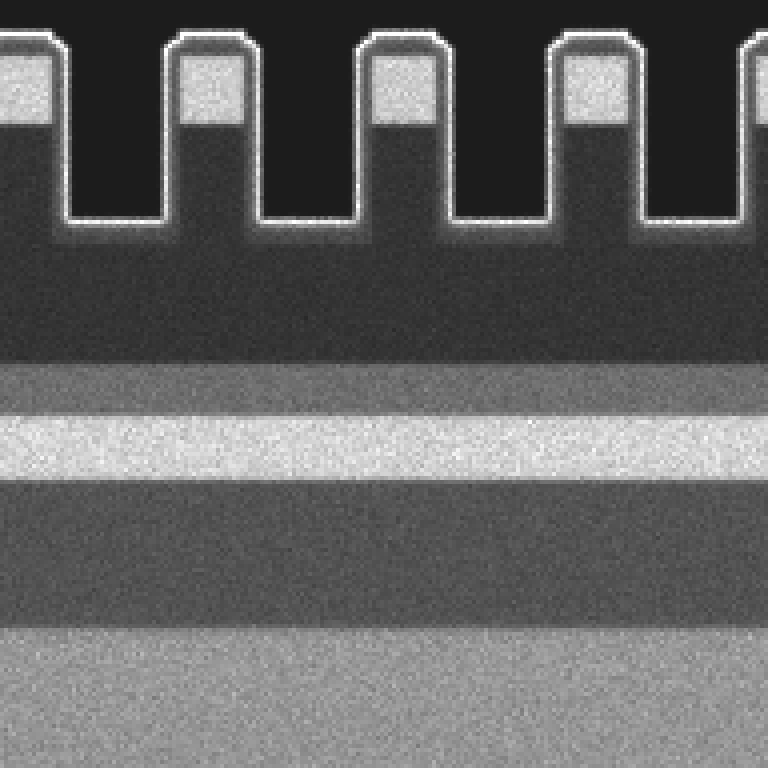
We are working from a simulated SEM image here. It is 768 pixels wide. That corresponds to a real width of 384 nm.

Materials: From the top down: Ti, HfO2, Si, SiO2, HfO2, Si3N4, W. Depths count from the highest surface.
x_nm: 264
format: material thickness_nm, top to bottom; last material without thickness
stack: empty 94, Ti 12, Si 60, SiO2 26, HfO2 32, Si3N4 74, W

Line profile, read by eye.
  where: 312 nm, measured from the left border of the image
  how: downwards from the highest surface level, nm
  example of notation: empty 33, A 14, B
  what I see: Ti 12, HfO2 34, Si 120, SiO2 26, HfO2 32, Si3N4 74, W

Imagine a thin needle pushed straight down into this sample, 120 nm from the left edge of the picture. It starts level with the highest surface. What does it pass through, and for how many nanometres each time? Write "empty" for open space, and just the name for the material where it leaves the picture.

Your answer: Ti 12, HfO2 34, Si 120, SiO2 26, HfO2 32, Si3N4 74, W